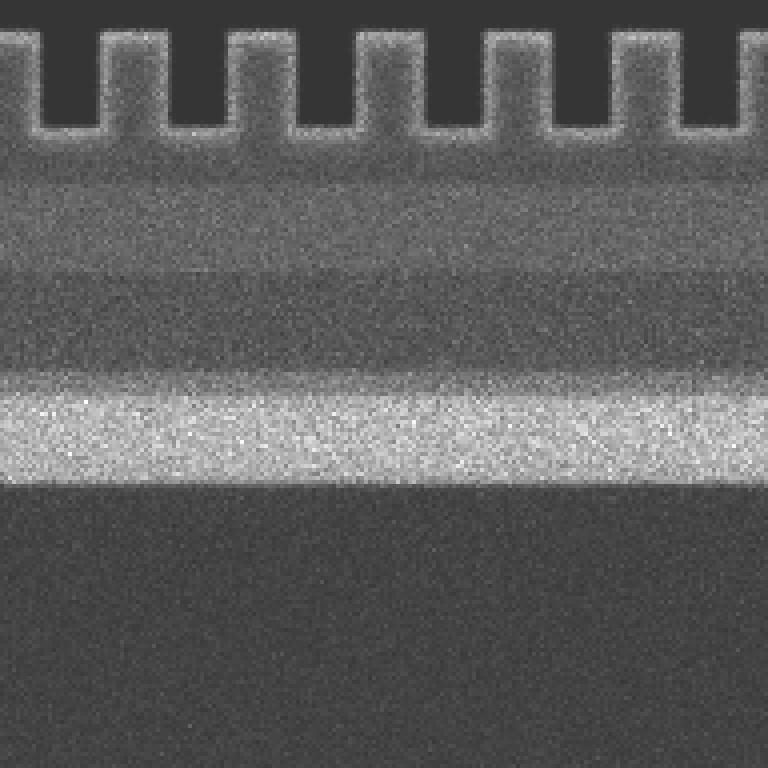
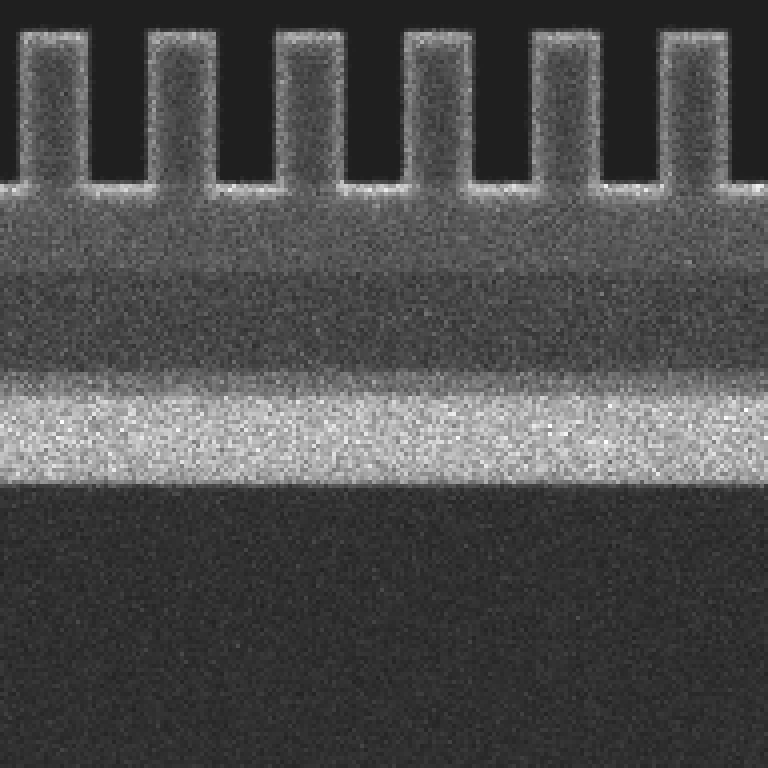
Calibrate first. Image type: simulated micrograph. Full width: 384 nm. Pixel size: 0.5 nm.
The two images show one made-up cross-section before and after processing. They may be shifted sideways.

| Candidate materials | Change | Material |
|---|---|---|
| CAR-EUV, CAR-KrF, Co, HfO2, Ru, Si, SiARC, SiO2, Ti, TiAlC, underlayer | removed | underlayer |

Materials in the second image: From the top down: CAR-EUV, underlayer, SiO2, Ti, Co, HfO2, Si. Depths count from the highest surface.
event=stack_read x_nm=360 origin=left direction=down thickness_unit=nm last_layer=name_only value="CAR-EUV 48, underlayer 28, SiO2 44, Ti 50, Co 12, HfO2 44, Si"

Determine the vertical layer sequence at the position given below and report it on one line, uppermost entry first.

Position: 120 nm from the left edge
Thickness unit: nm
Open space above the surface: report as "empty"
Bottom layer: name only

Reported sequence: empty 76, SiO2 44, Ti 50, Co 12, HfO2 44, Si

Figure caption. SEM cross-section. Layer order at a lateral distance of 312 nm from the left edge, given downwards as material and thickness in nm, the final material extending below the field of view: empty 76, SiO2 44, Ti 50, Co 12, HfO2 44, Si